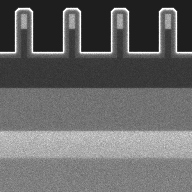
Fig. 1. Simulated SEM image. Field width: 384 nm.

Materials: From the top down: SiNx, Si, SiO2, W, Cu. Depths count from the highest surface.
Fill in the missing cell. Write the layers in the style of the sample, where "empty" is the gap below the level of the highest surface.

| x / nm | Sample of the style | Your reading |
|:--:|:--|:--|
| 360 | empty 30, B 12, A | empty 88, SiNx 12, Si 60, SiO2 86, W 54, Cu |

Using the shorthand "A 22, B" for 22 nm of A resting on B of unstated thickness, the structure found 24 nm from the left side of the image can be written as empty 88, SiNx 12, Si 60, SiO2 86, W 54, Cu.